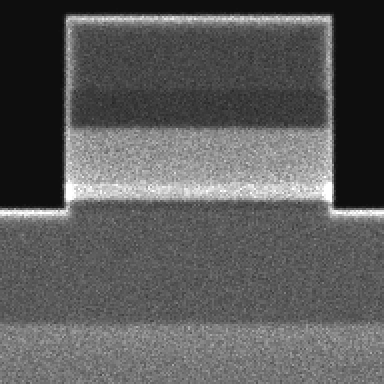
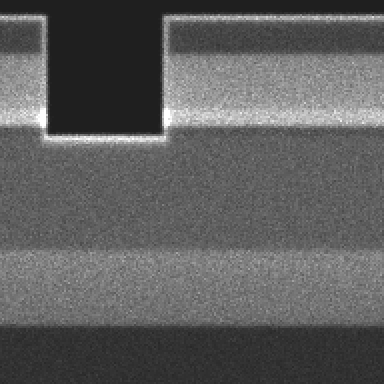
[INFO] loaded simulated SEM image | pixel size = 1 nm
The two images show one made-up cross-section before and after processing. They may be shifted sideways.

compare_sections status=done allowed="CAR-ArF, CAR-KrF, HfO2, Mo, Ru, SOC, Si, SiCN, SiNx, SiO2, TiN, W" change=removed material="SOC"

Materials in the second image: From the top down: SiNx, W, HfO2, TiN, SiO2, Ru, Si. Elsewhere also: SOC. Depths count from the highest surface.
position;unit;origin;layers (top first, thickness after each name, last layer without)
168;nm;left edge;SiNx 38, W 56, HfO2 16, TiN 10, SiO2 114, Ru 76, Si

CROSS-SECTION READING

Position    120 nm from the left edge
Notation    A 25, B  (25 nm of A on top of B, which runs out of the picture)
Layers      empty 120, SiO2 114, Ru 76, Si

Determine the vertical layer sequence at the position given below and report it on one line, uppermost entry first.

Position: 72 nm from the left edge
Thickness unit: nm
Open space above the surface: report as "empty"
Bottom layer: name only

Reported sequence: empty 120, SiO2 114, Ru 76, Si